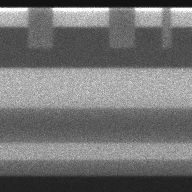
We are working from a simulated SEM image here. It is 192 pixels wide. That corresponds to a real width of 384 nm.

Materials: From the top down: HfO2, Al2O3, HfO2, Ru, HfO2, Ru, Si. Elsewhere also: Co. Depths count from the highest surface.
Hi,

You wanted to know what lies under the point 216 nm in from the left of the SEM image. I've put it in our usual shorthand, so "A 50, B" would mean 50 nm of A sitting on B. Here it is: HfO2 38, Al2O3 82, HfO2 80, Ru 70, HfO2 34, Ru 32, Si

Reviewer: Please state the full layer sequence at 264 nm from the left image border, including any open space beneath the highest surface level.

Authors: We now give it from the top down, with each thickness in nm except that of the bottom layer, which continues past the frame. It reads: Co 80, Al2O3 40, HfO2 80, Ru 70, HfO2 34, Ru 32, Si